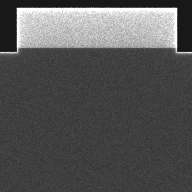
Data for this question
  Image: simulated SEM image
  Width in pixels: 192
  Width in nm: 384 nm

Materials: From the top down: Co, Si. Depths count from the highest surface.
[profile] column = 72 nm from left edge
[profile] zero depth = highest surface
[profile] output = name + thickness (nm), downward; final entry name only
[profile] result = Co 80, Si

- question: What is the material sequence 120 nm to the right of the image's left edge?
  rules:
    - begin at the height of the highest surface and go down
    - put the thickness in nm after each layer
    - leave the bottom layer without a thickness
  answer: Co 80, Si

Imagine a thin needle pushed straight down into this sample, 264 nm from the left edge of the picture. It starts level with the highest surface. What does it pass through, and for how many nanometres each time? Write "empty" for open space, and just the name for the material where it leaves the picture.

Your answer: Co 80, Si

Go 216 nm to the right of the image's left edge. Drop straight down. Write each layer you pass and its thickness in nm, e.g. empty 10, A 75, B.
Co 80, Si